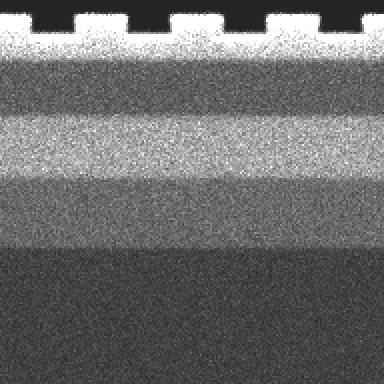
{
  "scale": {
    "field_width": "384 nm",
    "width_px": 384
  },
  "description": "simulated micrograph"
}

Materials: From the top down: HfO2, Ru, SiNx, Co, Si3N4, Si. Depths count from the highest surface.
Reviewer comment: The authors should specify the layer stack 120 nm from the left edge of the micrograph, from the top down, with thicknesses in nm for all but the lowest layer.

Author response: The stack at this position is HfO2 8, Ru 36, SiNx 56, Co 62, Si3N4 70, Si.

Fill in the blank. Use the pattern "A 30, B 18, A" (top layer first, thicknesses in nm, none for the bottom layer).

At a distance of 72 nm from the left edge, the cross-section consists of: empty 18, Ru 26, SiNx 56, Co 62, Si3N4 70, Si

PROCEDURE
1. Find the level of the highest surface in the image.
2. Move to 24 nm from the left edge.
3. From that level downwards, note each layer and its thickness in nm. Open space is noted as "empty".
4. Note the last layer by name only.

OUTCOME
HfO2 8, Ru 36, SiNx 56, Co 62, Si3N4 70, Si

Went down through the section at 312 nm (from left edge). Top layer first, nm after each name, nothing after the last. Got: HfO2 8, Ru 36, SiNx 56, Co 62, Si3N4 70, Si